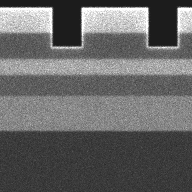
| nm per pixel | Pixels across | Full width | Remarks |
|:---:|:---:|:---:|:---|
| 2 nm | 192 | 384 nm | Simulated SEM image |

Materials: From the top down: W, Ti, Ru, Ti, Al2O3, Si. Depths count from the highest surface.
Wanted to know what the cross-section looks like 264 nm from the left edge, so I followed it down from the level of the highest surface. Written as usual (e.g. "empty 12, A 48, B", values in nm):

W 50, Ti 52, Ru 32, Ti 42, Al2O3 70, Si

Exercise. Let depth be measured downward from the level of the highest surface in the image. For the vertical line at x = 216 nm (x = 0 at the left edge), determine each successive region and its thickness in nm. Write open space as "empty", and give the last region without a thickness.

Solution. W 50, Ti 52, Ru 32, Ti 42, Al2O3 70, Si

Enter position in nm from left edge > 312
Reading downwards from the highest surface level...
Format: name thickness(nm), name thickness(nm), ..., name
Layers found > empty 78, Ti 24, Ru 32, Ti 42, Al2O3 70, Si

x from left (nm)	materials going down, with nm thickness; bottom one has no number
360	W 50, Ti 52, Ru 32, Ti 42, Al2O3 70, Si